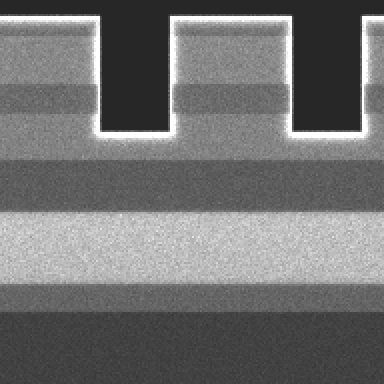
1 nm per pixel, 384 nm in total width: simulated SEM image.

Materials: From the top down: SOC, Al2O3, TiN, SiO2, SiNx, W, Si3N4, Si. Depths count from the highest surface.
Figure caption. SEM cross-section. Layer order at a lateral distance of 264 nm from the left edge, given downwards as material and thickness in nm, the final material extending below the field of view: SOC 20, Al2O3 48, TiN 30, SiO2 46, SiNx 52, W 72, Si3N4 28, Si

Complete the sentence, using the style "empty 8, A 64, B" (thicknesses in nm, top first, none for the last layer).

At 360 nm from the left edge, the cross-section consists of empty 116, SiO2 28, SiNx 52, W 72, Si3N4 28, Si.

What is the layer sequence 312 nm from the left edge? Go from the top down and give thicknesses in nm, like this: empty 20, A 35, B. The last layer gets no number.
empty 116, SiO2 28, SiNx 52, W 72, Si3N4 28, Si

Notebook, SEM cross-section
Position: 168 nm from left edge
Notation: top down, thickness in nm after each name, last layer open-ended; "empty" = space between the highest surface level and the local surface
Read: empty 116, SiO2 28, SiNx 52, W 72, Si3N4 28, Si